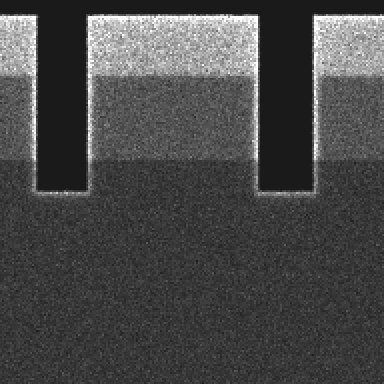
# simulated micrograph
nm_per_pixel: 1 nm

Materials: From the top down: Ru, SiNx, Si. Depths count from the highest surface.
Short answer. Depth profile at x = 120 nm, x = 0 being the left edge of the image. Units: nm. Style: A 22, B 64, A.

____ Ru 60, SiNx 84, Si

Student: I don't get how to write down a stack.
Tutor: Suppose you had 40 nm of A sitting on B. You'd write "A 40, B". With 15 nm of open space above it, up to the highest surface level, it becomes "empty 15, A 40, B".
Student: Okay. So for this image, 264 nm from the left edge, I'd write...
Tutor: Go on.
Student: empty 176, Si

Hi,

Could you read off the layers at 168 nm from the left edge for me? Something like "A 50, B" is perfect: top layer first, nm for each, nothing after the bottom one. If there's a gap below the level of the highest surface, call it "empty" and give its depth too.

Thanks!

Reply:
Ru 60, SiNx 84, Si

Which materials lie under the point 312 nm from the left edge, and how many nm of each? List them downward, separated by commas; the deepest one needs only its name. empty 176, Si